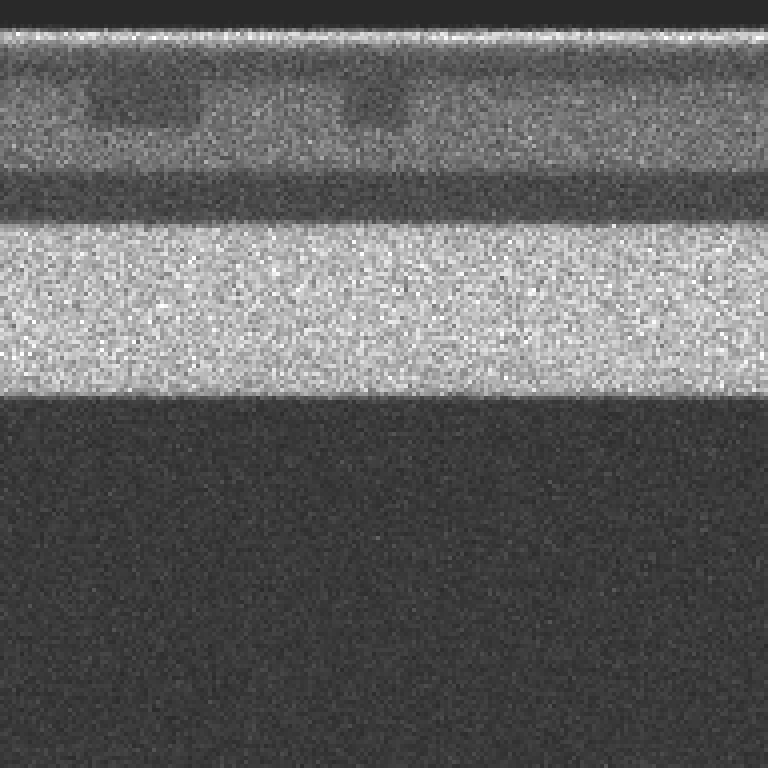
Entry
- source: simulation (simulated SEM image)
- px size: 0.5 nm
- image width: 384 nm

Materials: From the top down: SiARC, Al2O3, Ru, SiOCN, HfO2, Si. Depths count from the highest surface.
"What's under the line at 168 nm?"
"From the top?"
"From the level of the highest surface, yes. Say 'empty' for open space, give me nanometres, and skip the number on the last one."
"SiARC 24, Al2O3 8, Ru 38, SiOCN 26, HfO2 86, Si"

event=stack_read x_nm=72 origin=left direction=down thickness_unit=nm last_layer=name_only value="SiARC 48, Ru 22, SiOCN 26, HfO2 86, Si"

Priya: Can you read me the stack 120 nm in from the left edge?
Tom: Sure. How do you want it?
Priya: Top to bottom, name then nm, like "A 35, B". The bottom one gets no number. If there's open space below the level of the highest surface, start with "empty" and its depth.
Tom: SiARC 24, Al2O3 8, Ru 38, SiOCN 26, HfO2 86, Si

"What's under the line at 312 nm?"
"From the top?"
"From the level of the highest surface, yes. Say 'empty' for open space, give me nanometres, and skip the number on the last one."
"SiARC 24, Al2O3 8, Ru 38, SiOCN 26, HfO2 86, Si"